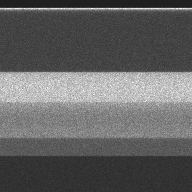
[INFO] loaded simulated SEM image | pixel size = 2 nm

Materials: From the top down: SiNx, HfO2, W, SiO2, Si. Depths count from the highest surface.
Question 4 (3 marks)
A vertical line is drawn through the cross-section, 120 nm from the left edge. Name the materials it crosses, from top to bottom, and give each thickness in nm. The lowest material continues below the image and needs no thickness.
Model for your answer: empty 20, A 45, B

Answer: SiNx 128, HfO2 60, W 72, SiO2 36, Si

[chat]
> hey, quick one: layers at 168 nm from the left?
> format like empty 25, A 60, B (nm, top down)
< SiNx 128, HfO2 60, W 72, SiO2 36, Si